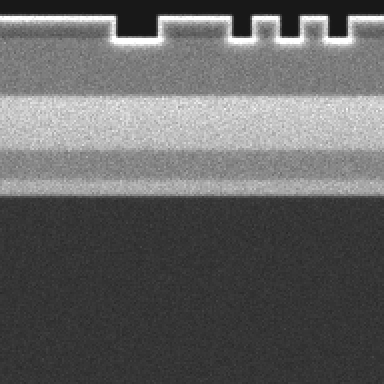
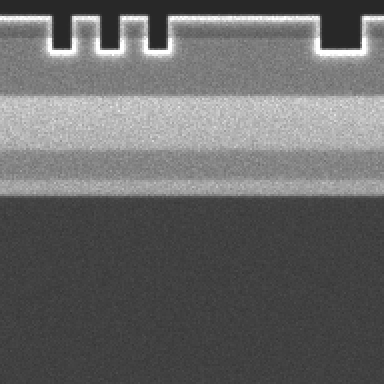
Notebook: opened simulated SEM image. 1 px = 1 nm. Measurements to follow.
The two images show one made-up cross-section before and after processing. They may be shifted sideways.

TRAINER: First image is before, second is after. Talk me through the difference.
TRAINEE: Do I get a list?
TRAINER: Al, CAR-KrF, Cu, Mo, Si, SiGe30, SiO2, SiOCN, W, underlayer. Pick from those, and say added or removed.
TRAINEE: removed: SiO2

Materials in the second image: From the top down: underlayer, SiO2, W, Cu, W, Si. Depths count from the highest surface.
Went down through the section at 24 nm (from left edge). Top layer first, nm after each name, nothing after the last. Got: underlayer 22, SiO2 58, W 54, Cu 30, W 16, Si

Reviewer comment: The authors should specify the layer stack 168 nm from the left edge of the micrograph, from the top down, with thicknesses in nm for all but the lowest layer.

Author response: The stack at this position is underlayer 22, SiO2 58, W 54, Cu 30, W 16, Si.